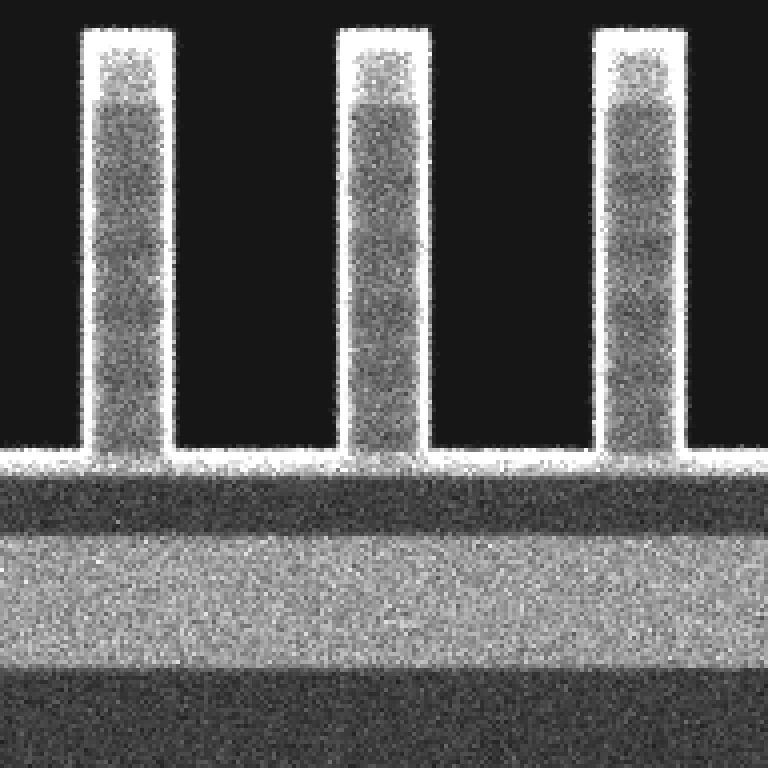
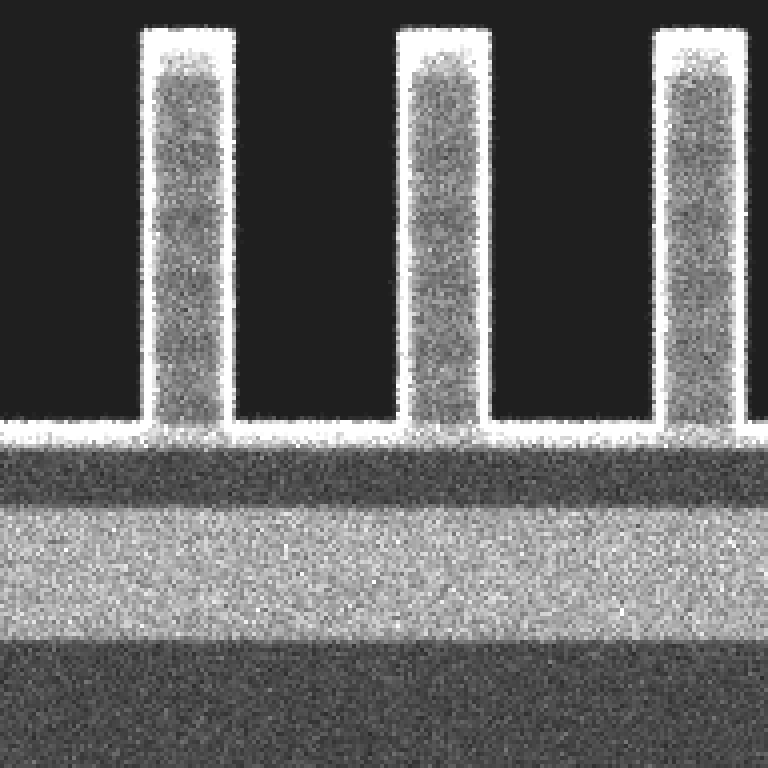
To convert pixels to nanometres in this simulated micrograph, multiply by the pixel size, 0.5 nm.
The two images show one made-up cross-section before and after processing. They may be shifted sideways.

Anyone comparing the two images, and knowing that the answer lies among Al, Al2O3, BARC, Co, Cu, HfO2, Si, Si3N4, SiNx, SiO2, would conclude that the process removed Al2O3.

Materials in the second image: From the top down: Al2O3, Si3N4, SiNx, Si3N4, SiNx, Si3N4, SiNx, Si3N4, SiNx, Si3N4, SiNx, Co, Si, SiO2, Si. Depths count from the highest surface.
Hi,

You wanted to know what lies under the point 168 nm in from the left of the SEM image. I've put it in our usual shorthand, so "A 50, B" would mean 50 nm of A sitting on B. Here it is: empty 196, Co 12, Si 30, SiO2 66, Si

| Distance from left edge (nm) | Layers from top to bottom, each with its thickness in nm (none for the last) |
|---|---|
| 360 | Al2O3 22, Si3N4 34, SiNx 12, Si3N4 20, SiNx 12, Si3N4 20, SiNx 12, Si3N4 20, SiNx 12, Si3N4 20, SiNx 12, Co 12, Si 30, SiO2 66, Si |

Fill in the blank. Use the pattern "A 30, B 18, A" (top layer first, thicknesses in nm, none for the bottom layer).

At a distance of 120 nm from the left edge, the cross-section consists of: empty 196, Co 12, Si 30, SiO2 66, Si